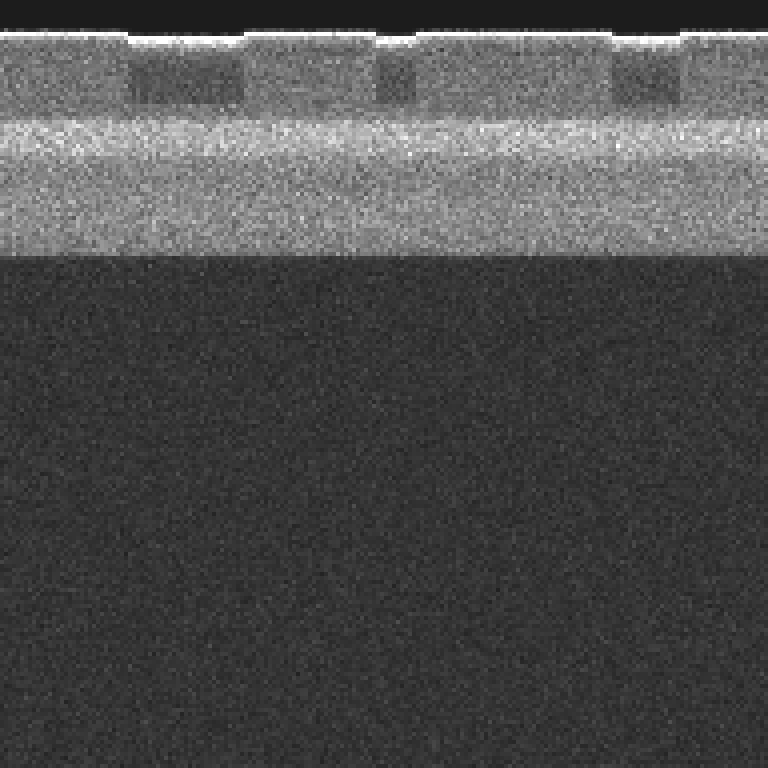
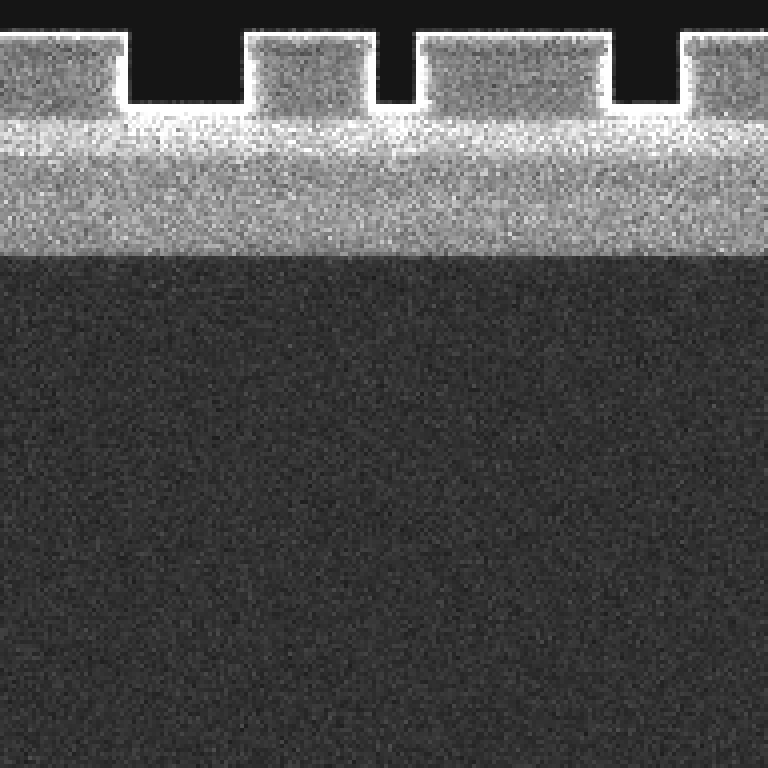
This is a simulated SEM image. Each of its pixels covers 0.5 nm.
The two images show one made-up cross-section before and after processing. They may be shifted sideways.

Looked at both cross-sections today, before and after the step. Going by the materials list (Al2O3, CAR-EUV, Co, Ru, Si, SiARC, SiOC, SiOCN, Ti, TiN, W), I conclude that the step removed SiARC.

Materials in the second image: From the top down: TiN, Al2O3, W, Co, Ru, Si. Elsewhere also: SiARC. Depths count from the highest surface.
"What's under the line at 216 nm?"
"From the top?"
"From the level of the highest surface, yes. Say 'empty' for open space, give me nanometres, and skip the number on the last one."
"TiN 12, Al2O3 32, W 18, Co 20, Ru 30, Si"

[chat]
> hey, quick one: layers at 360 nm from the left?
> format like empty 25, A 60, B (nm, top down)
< TiN 12, Al2O3 32, W 18, Co 20, Ru 30, Si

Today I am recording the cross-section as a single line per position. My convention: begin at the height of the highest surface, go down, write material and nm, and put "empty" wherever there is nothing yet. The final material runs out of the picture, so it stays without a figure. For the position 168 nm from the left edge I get TiN 12, Al2O3 32, W 18, Co 20, Ru 30, Si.